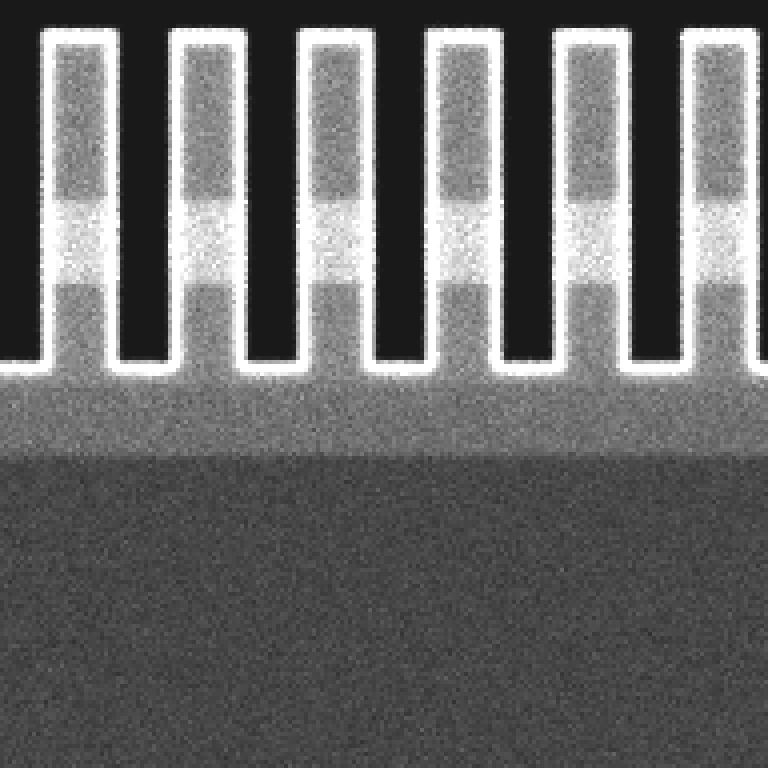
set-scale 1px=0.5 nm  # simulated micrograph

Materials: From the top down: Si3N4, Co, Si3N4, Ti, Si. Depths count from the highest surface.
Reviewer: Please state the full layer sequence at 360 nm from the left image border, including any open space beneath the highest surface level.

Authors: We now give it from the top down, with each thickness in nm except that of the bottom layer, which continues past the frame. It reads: Si3N4 84, Co 42, Si3N4 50, Ti 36, Si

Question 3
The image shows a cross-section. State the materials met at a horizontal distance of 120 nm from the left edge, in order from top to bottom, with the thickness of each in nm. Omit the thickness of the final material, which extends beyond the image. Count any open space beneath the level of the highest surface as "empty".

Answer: Si3N4 84, Co 42, Si3N4 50, Ti 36, Si